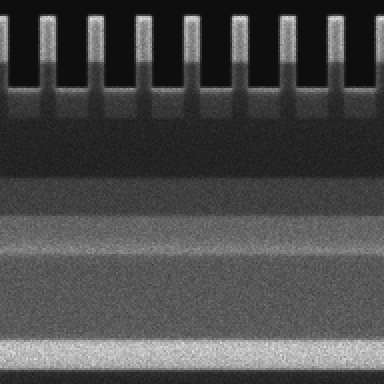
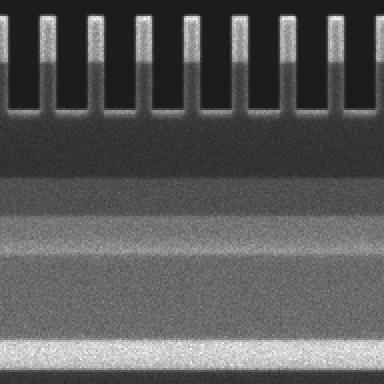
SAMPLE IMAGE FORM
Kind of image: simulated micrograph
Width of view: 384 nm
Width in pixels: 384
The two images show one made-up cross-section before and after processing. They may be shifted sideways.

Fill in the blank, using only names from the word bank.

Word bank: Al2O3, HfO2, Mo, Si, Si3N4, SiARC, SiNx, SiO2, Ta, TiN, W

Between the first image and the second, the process removed SiNx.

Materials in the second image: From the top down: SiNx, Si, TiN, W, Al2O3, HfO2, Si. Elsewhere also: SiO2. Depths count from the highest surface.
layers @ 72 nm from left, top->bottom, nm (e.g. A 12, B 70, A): empty 94, SiNx 8, Si 60, TiN 38, W 38, Al2O3 86, HfO2 30, Si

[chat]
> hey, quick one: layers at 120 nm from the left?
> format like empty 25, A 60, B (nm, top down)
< empty 94, SiNx 8, Si 60, TiN 38, W 38, Al2O3 86, HfO2 30, Si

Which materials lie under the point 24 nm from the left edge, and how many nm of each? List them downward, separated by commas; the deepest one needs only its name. empty 94, SiNx 8, Si 60, TiN 38, W 38, Al2O3 86, HfO2 30, Si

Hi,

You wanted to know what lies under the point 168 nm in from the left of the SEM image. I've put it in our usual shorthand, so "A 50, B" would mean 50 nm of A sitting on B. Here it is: empty 94, SiNx 8, Si 60, TiN 38, W 38, Al2O3 86, HfO2 30, Si